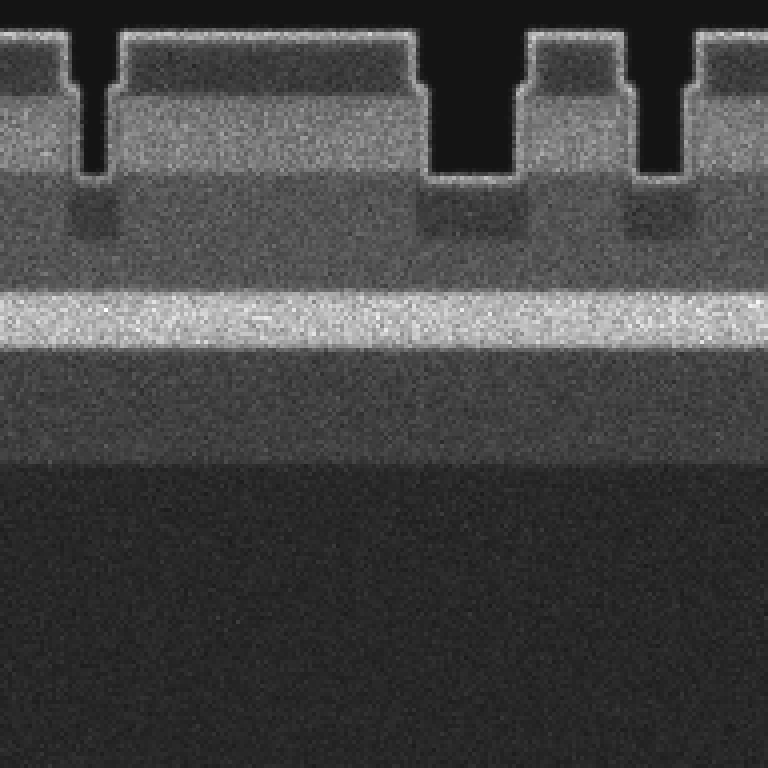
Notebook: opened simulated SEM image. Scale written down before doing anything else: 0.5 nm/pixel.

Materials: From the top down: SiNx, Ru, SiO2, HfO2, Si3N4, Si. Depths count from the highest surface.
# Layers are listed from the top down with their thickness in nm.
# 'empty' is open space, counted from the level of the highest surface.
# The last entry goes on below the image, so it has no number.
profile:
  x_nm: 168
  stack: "SiNx 32, Ru 38, SiO2 60, HfO2 28, Si3N4 58, Si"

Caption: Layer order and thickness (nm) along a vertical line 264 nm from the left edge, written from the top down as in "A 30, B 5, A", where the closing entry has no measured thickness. SiNx 32, Ru 38, SiO2 60, HfO2 28, Si3N4 58, Si